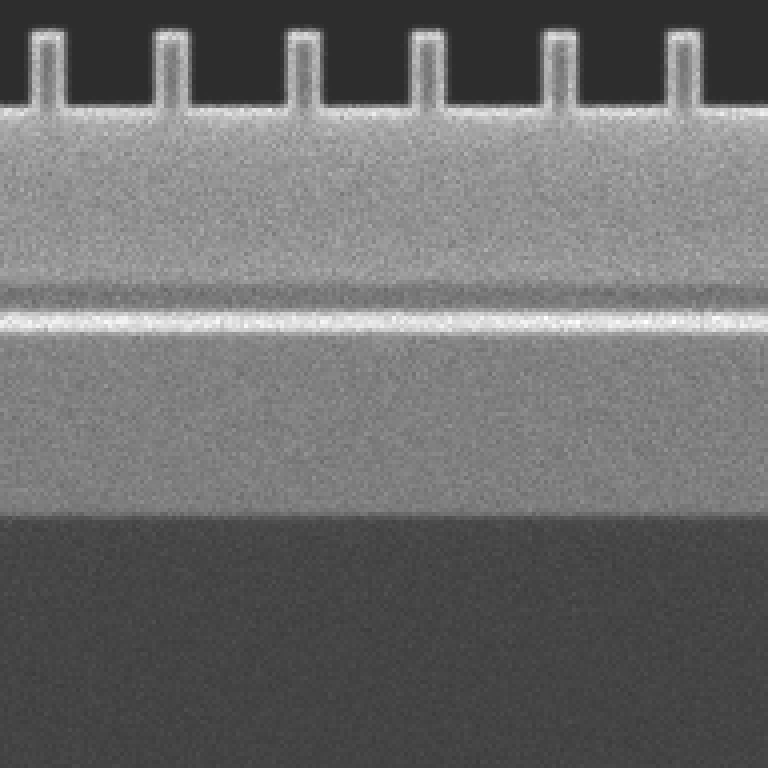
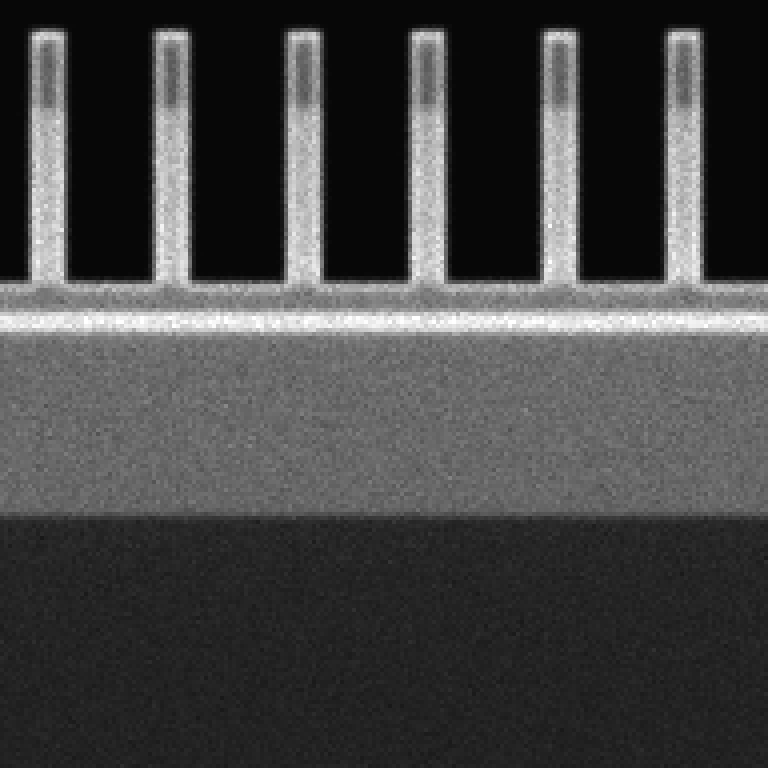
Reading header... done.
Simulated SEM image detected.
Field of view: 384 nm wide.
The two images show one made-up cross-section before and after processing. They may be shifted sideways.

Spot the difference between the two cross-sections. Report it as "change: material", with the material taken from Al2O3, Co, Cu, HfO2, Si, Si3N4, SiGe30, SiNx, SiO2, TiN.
removed: Co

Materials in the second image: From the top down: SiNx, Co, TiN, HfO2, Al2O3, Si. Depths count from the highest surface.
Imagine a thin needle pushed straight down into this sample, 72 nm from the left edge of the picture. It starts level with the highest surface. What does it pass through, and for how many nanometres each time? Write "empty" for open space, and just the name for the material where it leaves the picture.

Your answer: empty 126, TiN 14, HfO2 10, Al2O3 92, Si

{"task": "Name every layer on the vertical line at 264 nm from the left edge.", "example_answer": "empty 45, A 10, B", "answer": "empty 126, TiN 14, HfO2 10, Al2O3 92, Si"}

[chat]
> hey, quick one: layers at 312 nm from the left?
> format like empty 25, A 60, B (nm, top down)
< empty 126, TiN 14, HfO2 10, Al2O3 92, Si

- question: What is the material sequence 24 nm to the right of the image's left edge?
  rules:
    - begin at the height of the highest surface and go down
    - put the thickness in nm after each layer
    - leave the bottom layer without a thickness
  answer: SiNx 38, Co 88, TiN 14, HfO2 10, Al2O3 92, Si